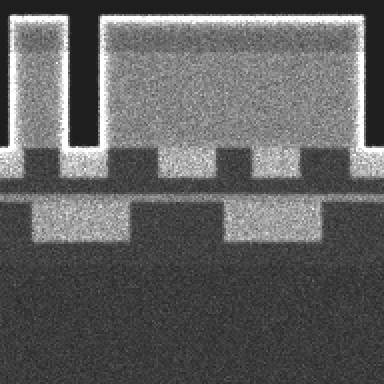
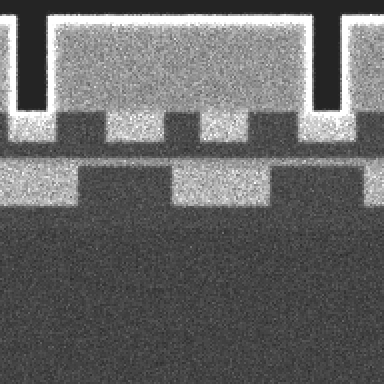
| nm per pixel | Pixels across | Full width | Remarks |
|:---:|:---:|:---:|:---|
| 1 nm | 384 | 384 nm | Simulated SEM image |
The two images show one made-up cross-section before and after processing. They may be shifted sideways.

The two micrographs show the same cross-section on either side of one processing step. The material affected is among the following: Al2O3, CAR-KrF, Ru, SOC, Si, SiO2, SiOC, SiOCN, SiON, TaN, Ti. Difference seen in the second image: SOC removed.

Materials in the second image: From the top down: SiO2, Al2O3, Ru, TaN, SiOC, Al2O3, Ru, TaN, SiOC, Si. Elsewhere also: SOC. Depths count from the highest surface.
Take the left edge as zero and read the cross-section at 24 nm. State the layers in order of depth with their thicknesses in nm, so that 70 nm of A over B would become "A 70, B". empty 96, Ru 22, TaN 8, SiOC 16, Al2O3 8, Ru 32, TaN 8, SiOC 24, Si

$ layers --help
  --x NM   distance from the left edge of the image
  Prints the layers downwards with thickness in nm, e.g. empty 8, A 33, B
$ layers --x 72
SiO2 88, Al2O3 8, SiOC 46, Al2O3 8, TaN 40, SiOC 24, Si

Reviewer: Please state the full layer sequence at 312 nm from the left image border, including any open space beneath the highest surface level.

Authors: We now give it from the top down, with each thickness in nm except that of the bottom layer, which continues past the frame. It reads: empty 96, Ru 22, TaN 8, SiOC 16, Al2O3 8, SiOC 64, Si